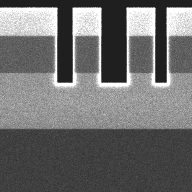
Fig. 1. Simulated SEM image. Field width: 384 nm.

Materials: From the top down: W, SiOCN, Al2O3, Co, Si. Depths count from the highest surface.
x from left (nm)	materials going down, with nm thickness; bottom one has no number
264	W 56, SiOCN 74, Al2O3 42, Co 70, Si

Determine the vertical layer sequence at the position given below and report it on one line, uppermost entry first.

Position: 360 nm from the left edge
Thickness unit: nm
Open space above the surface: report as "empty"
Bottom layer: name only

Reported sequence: W 56, SiOCN 74, Al2O3 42, Co 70, Si